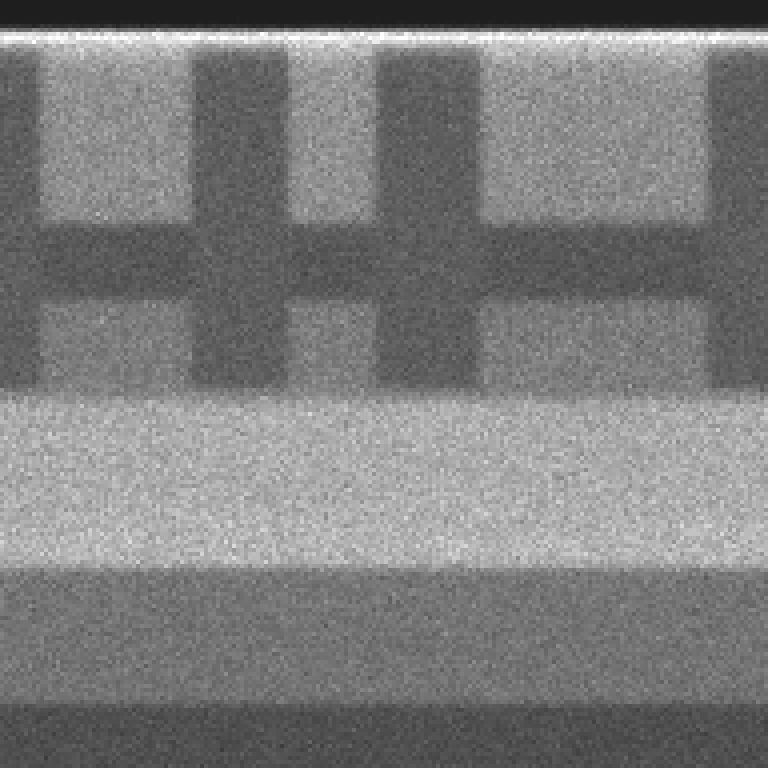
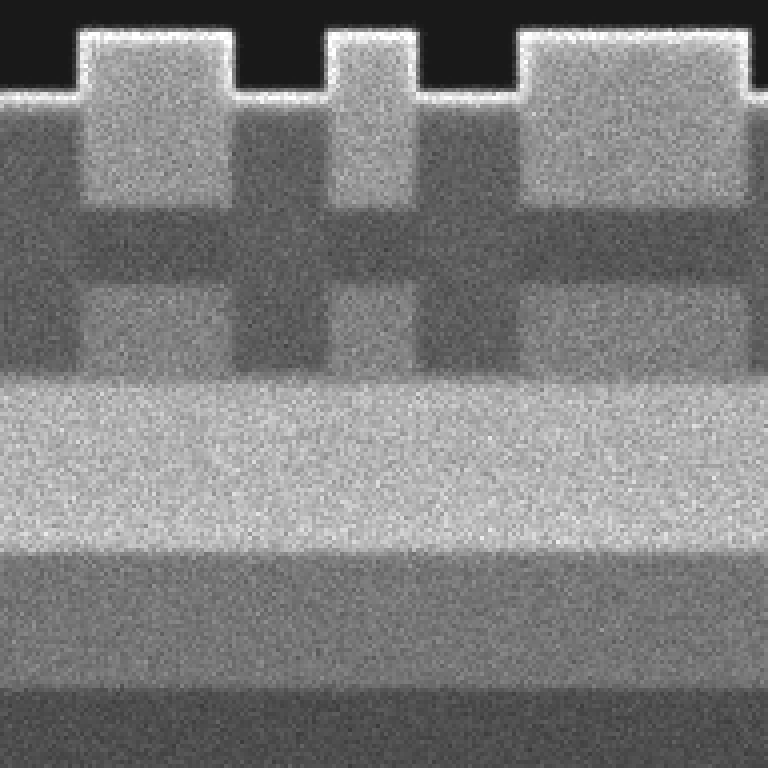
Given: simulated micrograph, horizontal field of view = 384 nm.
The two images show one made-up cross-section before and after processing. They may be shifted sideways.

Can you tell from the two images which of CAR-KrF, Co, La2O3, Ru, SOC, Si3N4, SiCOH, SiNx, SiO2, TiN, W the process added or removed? Yes, it removed SOC.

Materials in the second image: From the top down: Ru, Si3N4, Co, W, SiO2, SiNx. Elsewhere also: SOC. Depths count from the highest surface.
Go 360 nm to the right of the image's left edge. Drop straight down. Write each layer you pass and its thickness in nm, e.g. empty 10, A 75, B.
Ru 88, Si3N4 38, Co 50, W 84, SiO2 68, SiNx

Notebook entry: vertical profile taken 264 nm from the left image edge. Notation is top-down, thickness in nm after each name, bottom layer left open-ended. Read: Ru 88, Si3N4 38, Co 50, W 84, SiO2 68, SiNx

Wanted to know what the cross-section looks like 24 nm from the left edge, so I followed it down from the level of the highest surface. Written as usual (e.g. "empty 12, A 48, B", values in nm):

empty 30, SOC 140, Co 6, W 84, SiO2 68, SiNx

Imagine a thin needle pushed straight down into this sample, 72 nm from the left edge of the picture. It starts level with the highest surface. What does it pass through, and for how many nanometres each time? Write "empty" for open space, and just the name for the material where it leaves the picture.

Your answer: Ru 88, Si3N4 38, Co 50, W 84, SiO2 68, SiNx